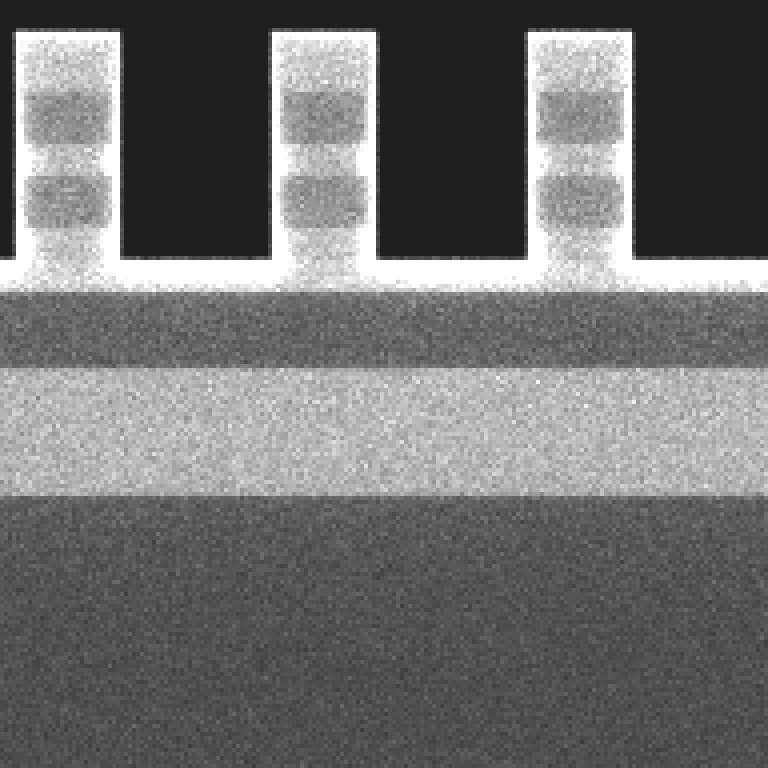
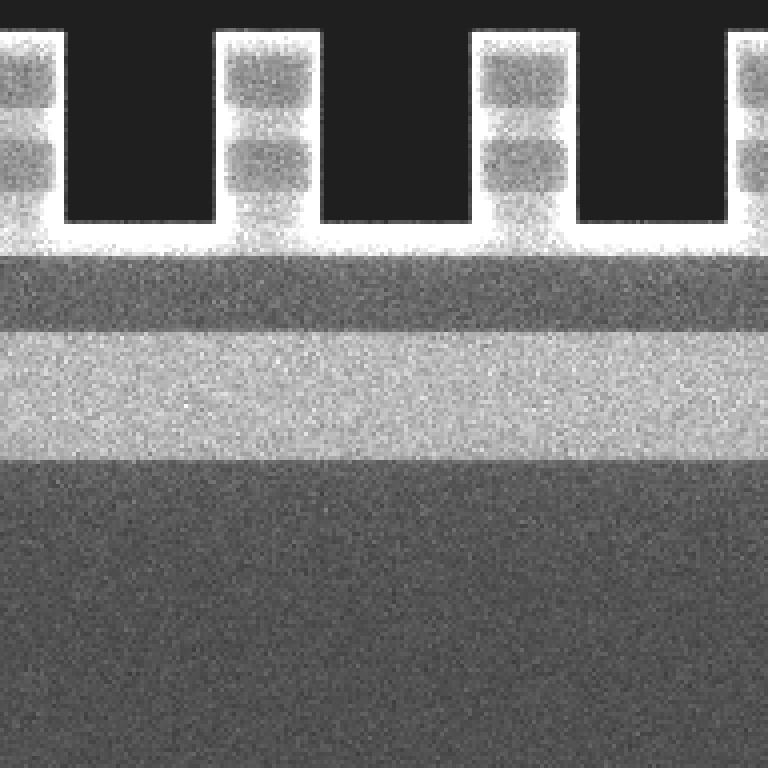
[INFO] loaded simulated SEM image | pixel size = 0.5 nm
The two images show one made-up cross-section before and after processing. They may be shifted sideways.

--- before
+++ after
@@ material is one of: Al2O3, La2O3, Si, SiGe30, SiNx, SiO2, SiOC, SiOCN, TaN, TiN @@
TiN removed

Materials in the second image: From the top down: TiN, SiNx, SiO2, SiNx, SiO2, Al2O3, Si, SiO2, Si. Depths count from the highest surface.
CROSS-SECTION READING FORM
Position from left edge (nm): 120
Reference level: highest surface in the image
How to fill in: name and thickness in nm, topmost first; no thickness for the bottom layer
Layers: TiN 12, SiNx 26, SiO2 16, SiNx 26, SiO2 16, Al2O3 16, Si 38, SiO2 64, Si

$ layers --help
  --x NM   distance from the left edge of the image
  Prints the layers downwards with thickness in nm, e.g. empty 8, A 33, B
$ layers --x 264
TiN 12, SiNx 26, SiO2 16, SiNx 26, SiO2 16, Al2O3 16, Si 38, SiO2 64, Si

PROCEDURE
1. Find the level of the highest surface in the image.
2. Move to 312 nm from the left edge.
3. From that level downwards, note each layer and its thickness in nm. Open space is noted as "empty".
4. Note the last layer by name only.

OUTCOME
empty 96, Al2O3 16, Si 38, SiO2 64, Si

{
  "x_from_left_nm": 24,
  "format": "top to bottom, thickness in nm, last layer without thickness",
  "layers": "TiN 12, SiNx 26, SiO2 16, SiNx 26, SiO2 16, Al2O3 16, Si 38, SiO2 64, Si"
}